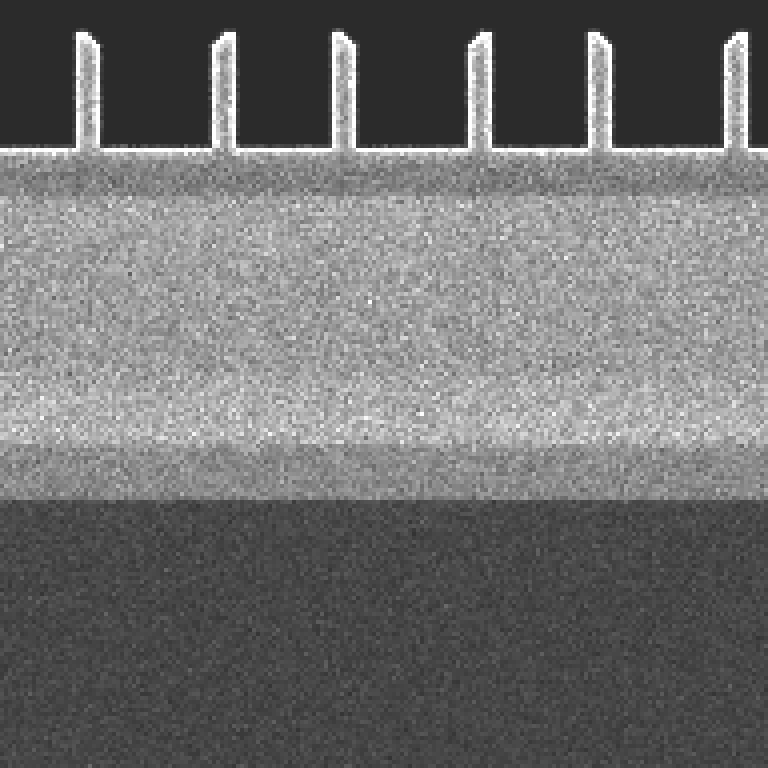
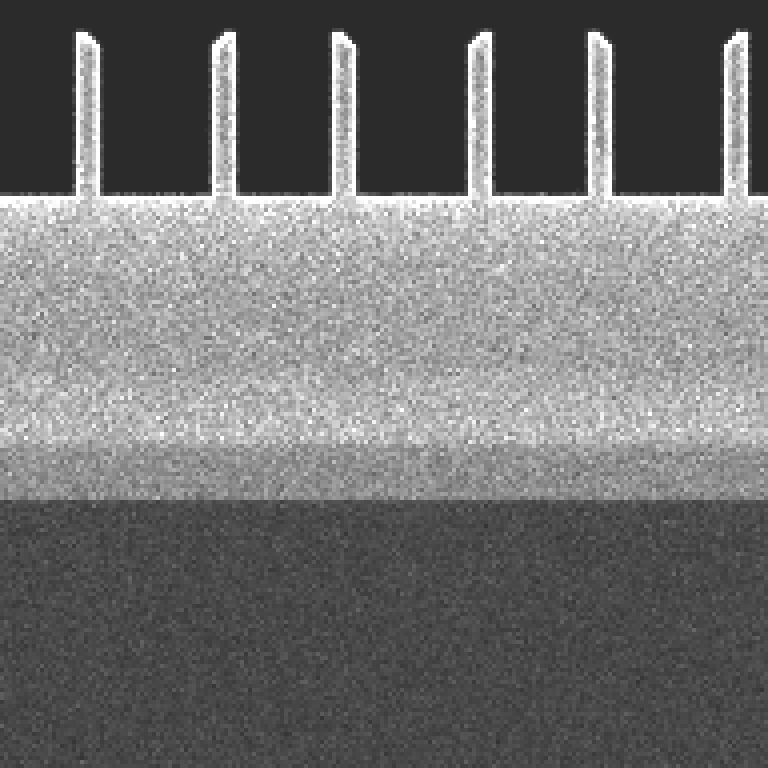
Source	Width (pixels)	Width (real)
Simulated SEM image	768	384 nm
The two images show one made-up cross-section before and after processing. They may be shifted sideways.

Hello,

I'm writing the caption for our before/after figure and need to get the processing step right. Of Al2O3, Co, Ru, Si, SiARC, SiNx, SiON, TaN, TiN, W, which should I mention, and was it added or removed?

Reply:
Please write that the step removed TiN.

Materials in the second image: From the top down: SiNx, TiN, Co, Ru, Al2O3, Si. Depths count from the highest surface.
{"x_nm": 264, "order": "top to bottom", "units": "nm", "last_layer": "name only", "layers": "empty 82, Co 90, Ru 34, Al2O3 28, Si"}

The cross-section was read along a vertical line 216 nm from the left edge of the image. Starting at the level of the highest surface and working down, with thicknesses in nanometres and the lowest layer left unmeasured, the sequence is empty 82, Co 90, Ru 34, Al2O3 28, Si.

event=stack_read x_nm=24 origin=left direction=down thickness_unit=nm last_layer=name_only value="empty 82, Co 90, Ru 34, Al2O3 28, Si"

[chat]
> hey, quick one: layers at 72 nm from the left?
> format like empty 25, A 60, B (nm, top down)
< empty 82, Co 90, Ru 34, Al2O3 28, Si